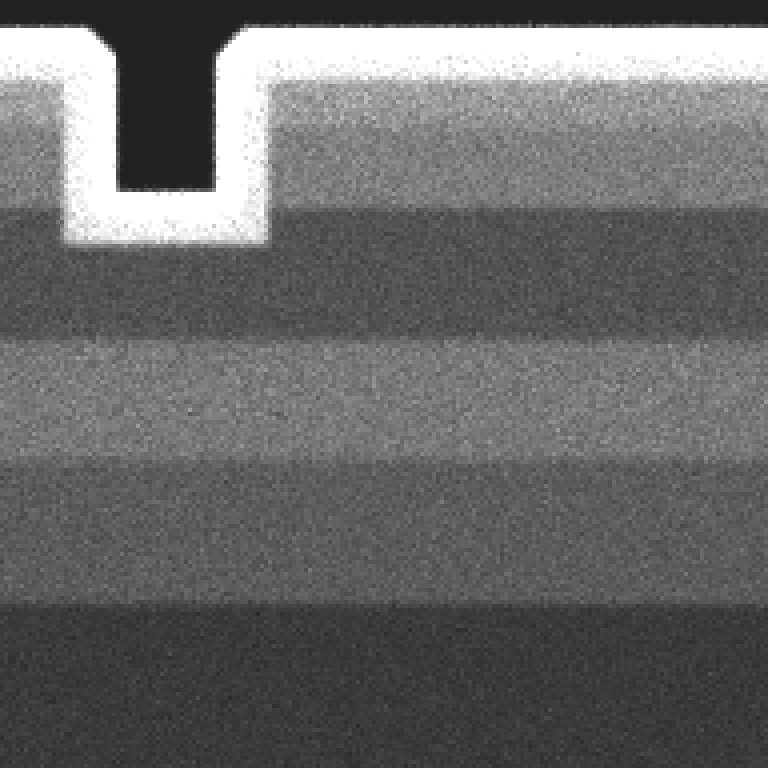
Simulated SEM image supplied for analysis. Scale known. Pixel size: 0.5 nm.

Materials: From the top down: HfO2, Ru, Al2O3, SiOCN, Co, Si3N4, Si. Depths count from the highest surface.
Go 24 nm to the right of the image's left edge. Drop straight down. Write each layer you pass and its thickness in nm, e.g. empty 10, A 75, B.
HfO2 24, Ru 24, Al2O3 40, SiOCN 66, Co 60, Si3N4 72, Si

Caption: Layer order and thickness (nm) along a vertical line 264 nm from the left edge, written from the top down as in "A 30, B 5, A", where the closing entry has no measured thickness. HfO2 24, Ru 24, Al2O3 40, SiOCN 66, Co 60, Si3N4 72, Si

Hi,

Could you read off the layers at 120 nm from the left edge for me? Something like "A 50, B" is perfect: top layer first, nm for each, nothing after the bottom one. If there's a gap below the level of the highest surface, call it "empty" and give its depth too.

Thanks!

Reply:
empty 2, HfO2 104, SiOCN 48, Co 60, Si3N4 72, Si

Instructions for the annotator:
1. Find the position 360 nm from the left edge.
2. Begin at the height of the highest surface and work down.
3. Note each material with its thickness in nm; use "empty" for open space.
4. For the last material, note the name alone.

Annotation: HfO2 24, Ru 24, Al2O3 40, SiOCN 66, Co 60, Si3N4 72, Si